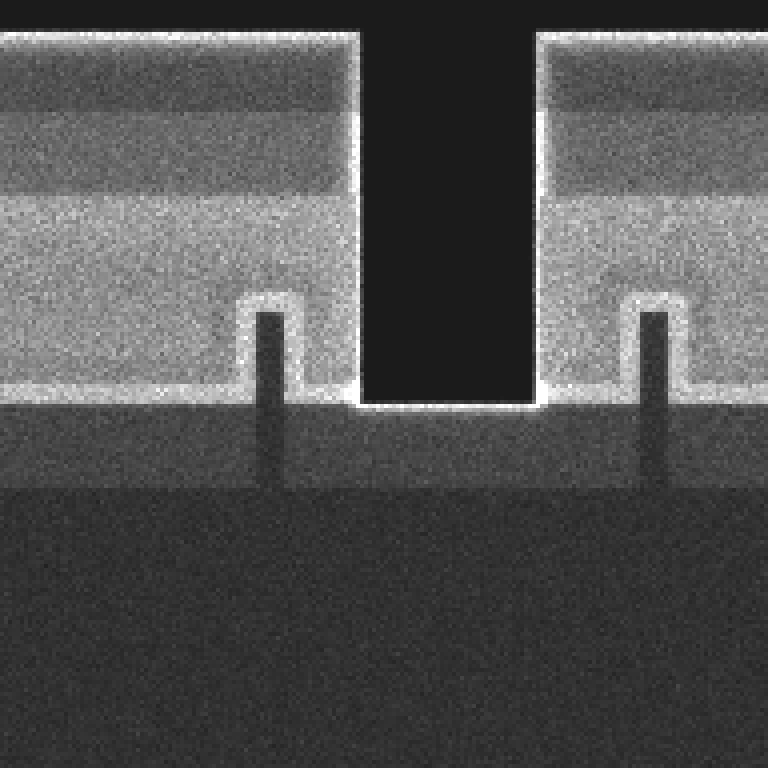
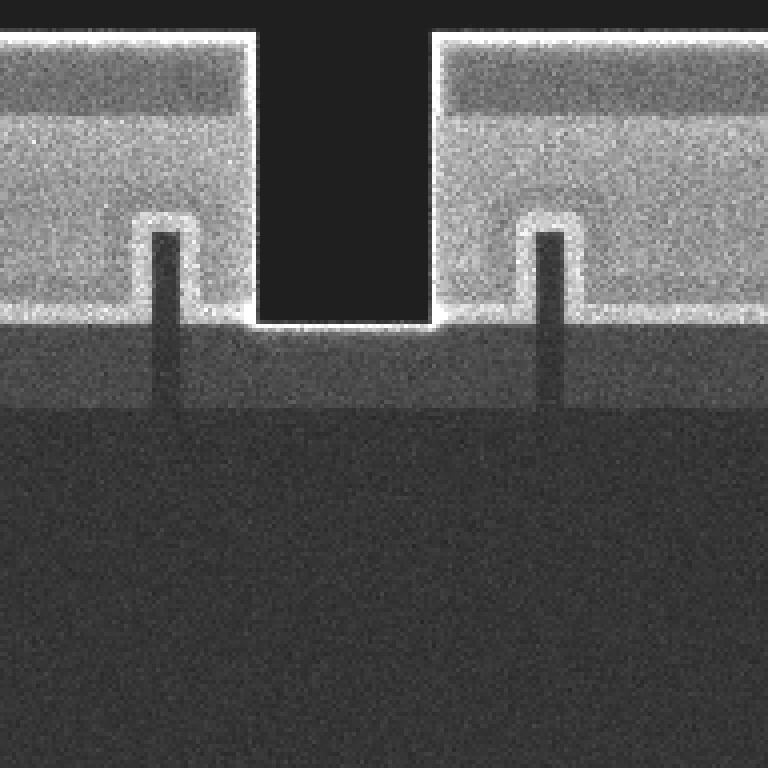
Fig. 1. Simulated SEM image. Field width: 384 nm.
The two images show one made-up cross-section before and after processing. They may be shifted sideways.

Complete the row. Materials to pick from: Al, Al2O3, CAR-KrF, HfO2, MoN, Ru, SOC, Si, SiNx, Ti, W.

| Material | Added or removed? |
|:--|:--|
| SOC | removed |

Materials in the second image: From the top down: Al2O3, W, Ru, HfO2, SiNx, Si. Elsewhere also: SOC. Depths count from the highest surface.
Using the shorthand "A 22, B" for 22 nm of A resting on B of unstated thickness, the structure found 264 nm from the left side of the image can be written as Al2O3 42, W 34, Ru 14, HfO2 56, SiNx 42, Si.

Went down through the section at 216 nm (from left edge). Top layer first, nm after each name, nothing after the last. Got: Al2O3 42, W 80, Ru 14, HfO2 10, SiNx 42, Si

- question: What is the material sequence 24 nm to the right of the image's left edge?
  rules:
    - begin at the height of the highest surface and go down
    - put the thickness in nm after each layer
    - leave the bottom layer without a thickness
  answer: Al2O3 42, W 80, Ru 14, HfO2 10, SiNx 42, Si